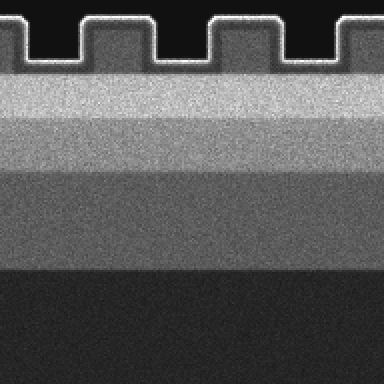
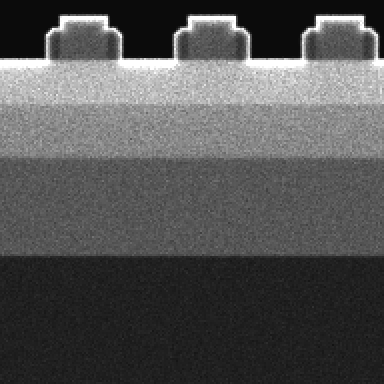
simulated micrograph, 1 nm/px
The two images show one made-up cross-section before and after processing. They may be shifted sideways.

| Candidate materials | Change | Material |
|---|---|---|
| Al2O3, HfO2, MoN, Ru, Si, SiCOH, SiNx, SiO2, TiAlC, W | removed | SiNx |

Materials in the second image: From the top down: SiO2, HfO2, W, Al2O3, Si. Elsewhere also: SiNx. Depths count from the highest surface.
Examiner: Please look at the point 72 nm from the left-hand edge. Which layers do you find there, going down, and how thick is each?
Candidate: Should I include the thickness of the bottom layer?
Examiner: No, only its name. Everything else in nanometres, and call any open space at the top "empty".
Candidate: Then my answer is SiO2 44, HfO2 44, W 54, Al2O3 98, Si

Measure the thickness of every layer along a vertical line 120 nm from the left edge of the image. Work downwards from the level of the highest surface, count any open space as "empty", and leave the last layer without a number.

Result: empty 18, SiNx 26, HfO2 44, W 54, Al2O3 98, Si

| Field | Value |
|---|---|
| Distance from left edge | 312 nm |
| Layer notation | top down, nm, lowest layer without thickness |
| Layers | empty 12, SiNx 32, HfO2 44, W 54, Al2O3 98, Si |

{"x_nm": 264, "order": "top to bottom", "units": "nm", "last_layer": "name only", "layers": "empty 44, HfO2 44, W 54, Al2O3 98, Si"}